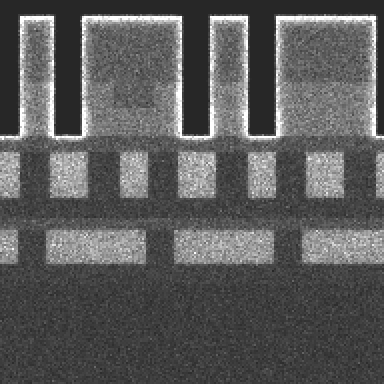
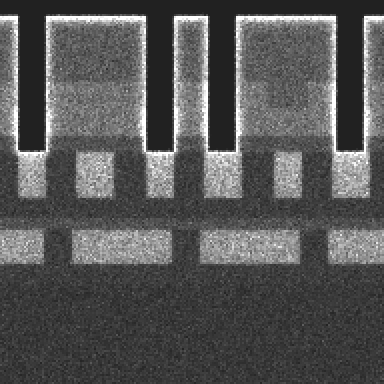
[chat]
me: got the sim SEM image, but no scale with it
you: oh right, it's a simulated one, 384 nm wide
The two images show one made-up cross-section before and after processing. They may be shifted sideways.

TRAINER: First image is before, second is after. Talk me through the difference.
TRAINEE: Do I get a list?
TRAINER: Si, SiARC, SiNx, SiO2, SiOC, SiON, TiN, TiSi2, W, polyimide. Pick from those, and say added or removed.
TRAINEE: removed: SiNx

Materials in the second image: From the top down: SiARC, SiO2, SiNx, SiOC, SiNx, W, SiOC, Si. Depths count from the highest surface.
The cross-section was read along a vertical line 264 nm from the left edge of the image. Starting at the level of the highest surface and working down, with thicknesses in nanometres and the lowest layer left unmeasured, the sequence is SiARC 66, SiO2 54, SiNx 16, SiOC 66, SiNx 12, W 34, SiOC 20, Si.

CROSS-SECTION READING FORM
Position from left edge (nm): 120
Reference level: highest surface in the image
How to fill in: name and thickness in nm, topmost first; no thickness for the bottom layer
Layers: SiARC 66, SiO2 54, SiNx 16, SiOC 66, SiNx 12, W 34, SiOC 20, Si